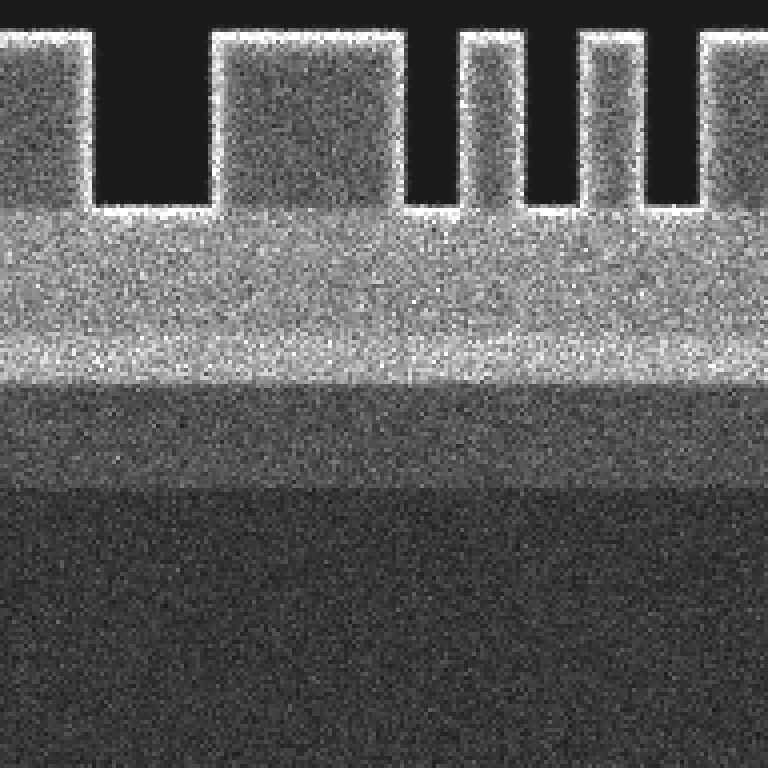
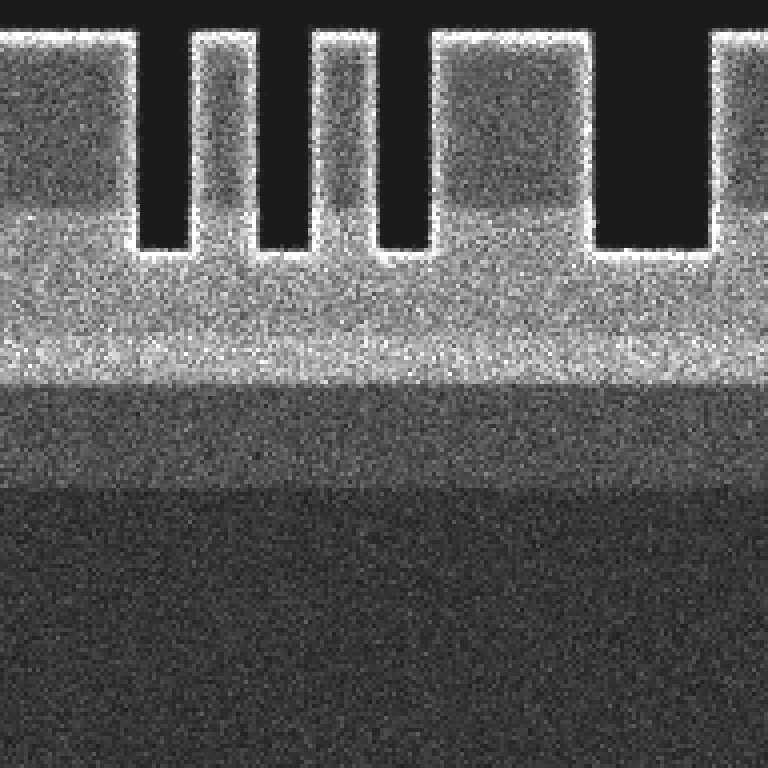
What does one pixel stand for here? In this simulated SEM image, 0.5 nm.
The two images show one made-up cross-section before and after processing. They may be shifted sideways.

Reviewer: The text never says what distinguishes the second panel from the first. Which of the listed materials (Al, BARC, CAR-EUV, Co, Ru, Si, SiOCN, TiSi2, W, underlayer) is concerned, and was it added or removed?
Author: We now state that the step removed Ru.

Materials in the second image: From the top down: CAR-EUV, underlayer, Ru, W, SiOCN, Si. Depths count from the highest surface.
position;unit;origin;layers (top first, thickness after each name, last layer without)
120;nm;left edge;CAR-EUV 58, underlayer 30, Ru 64, W 24, SiOCN 52, Si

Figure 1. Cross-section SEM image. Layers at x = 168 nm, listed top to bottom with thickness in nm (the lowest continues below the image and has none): CAR-EUV 58, underlayer 30, Ru 64, W 24, SiOCN 52, Si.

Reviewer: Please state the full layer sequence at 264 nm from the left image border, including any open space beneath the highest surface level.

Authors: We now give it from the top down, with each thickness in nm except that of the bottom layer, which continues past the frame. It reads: CAR-EUV 58, underlayer 30, Ru 64, W 24, SiOCN 52, Si